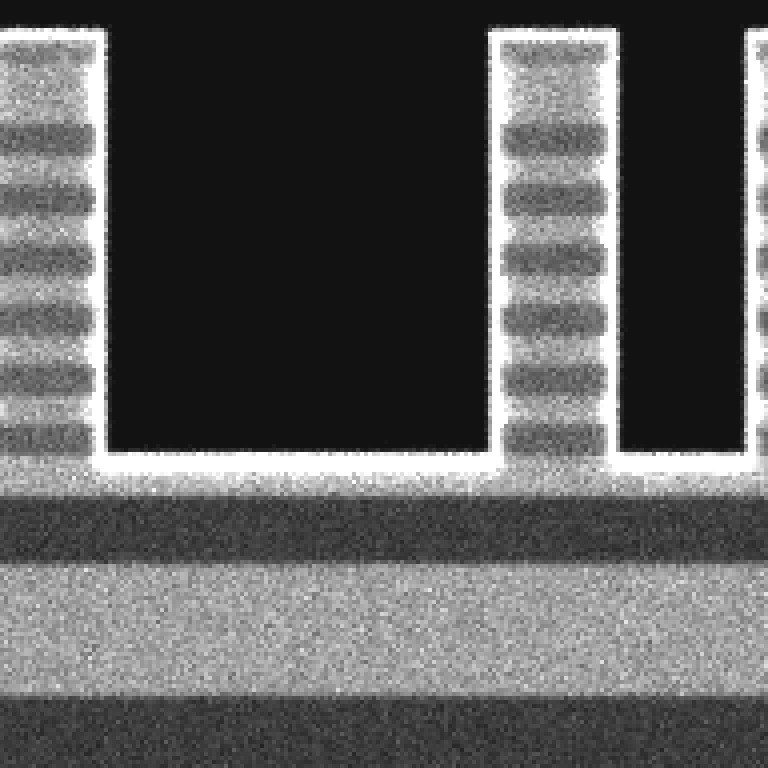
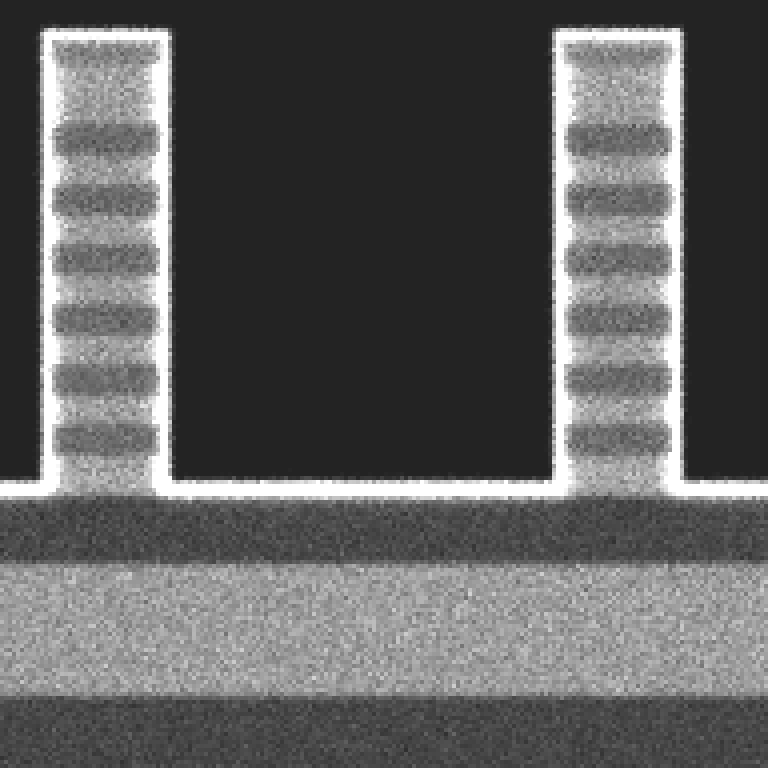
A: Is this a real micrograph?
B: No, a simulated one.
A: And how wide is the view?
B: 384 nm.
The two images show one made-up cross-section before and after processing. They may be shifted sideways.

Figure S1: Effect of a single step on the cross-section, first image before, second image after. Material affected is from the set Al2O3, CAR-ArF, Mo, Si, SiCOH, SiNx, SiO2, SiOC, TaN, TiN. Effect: removed Al2O3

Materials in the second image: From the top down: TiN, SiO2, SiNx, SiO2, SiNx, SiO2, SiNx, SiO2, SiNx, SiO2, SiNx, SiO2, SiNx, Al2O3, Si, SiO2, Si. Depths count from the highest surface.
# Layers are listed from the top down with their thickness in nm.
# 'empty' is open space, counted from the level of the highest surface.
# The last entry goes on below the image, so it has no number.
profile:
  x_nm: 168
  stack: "empty 226, Al2O3 6, Si 34, SiO2 66, Si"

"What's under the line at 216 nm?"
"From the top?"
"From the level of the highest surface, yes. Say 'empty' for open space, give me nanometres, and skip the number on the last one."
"empty 226, Al2O3 6, Si 34, SiO2 66, Si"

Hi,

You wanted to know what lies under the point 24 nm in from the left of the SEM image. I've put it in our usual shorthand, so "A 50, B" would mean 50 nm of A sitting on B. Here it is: TiN 16, SiO2 30, SiNx 16, SiO2 14, SiNx 16, SiO2 14, SiNx 16, SiO2 14, SiNx 16, SiO2 14, SiNx 16, SiO2 14, SiNx 16, Al2O3 20, Si 34, SiO2 66, Si